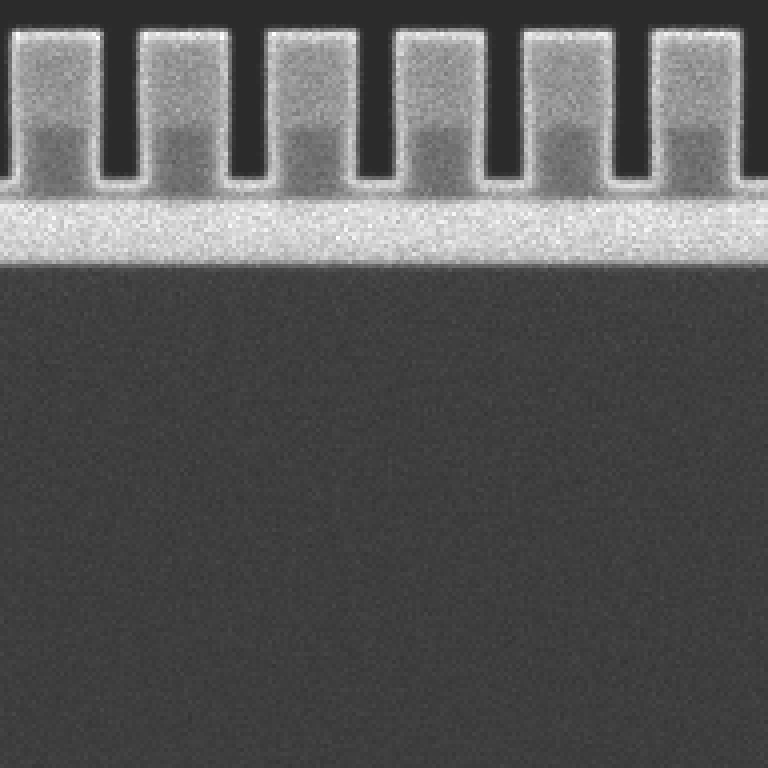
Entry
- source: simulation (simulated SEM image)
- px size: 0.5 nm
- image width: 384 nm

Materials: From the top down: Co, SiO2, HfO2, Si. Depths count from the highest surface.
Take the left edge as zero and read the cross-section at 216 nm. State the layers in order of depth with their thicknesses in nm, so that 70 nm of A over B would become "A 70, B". Co 48, SiO2 36, HfO2 32, Si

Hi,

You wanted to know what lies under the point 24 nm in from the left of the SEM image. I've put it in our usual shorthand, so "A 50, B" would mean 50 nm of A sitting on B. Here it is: Co 48, SiO2 36, HfO2 32, Si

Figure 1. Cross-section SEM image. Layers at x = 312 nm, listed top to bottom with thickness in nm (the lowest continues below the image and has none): empty 74, SiO2 10, HfO2 32, Si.